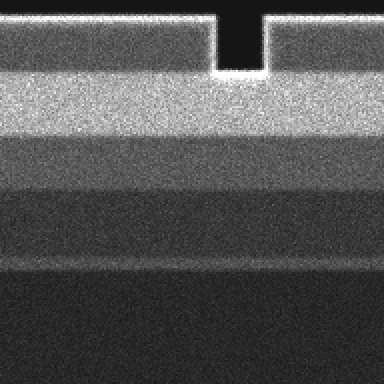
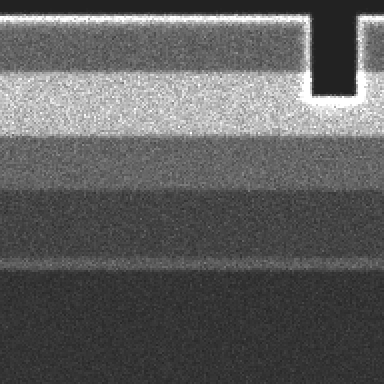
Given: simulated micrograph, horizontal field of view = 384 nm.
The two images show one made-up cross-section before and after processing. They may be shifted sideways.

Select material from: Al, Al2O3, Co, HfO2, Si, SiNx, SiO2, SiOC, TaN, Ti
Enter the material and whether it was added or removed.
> HfO2 / removed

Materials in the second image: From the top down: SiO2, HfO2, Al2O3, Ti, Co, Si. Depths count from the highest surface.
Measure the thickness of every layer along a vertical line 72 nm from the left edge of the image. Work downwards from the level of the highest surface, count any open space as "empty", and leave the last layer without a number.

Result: SiO2 56, HfO2 64, Al2O3 54, Ti 68, Co 12, Si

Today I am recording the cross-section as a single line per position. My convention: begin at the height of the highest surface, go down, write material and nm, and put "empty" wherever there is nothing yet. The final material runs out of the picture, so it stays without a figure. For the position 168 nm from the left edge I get SiO2 56, HfO2 64, Al2O3 54, Ti 68, Co 12, Si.